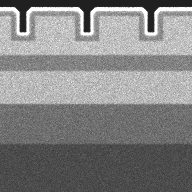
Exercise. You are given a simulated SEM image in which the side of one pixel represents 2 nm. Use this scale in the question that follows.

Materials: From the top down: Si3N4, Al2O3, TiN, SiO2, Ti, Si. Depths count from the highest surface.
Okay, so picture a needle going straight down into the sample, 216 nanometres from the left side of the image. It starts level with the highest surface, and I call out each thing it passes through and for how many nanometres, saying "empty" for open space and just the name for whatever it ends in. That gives Si3N4 16, Al2O3 78, TiN 32, SiO2 66, Ti 80, Si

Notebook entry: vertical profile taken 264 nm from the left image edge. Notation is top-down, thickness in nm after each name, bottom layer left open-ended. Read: Si3N4 16, Al2O3 78, TiN 32, SiO2 66, Ti 80, Si